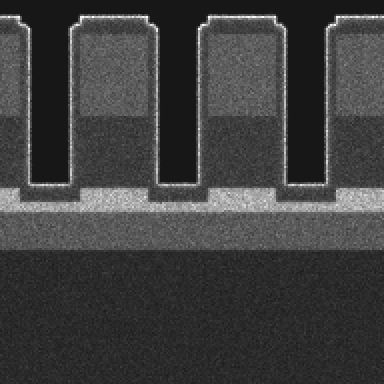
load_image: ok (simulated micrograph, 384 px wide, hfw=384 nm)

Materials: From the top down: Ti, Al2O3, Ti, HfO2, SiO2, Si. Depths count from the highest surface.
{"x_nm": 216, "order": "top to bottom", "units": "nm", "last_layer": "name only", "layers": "Ti 18, Al2O3 82, Ti 72, HfO2 24, SiO2 38, Si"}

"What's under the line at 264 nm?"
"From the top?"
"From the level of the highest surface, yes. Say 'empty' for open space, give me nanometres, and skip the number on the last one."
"Ti 18, Al2O3 82, Ti 72, HfO2 24, SiO2 38, Si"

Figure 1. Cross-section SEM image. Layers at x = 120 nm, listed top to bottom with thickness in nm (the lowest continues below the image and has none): Ti 18, Al2O3 82, Ti 72, HfO2 24, SiO2 38, Si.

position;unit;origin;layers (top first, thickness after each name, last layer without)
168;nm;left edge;empty 168, Ti 18, HfO2 10, SiO2 38, Si